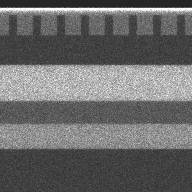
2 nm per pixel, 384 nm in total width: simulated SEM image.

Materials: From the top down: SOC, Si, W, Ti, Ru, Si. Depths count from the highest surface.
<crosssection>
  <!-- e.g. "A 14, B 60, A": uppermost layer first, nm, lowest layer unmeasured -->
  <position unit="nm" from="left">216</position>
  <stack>SOC 14, Si 100, W 72, Ti 46, Ru 50, Si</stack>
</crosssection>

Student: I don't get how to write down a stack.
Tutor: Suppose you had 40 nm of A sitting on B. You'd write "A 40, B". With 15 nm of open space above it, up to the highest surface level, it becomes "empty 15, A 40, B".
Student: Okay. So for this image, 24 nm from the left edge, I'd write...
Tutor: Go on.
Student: SOC 14, Si 100, W 72, Ti 46, Ru 50, Si